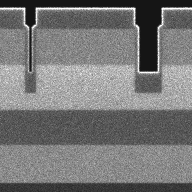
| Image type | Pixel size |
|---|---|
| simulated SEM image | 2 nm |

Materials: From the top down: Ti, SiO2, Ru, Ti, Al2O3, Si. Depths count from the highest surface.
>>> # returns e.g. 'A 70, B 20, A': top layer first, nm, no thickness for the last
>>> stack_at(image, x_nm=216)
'Ti 42, SiO2 72, Ru 90, Ti 70, Al2O3 76, Si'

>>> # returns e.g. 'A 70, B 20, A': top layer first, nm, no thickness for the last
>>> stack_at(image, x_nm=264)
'Ti 42, SiO2 72, Ru 90, Ti 70, Al2O3 76, Si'